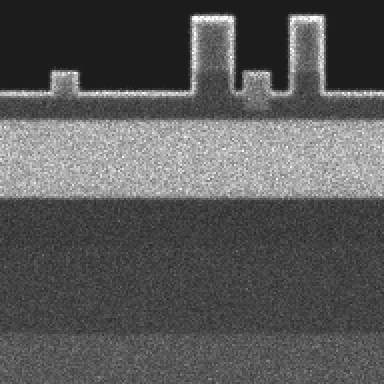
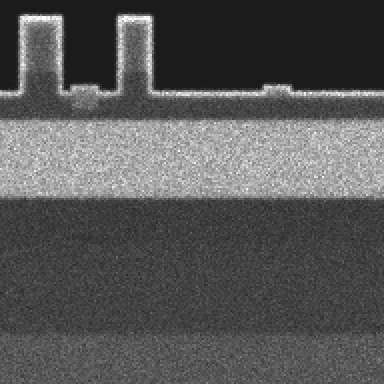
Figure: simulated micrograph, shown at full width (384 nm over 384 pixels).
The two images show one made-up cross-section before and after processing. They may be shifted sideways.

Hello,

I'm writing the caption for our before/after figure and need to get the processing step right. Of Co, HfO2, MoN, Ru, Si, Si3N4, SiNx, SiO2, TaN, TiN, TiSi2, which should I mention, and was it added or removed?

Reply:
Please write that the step removed Ru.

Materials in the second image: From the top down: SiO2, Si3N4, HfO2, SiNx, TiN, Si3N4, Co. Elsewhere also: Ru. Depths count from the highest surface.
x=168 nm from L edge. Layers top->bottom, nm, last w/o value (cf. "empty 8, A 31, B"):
empty 76, Si3N4 28, HfO2 78, SiNx 46, TiN 24, Si3N4 66, Co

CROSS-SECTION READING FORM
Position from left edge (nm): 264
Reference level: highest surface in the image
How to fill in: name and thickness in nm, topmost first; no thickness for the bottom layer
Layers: empty 70, Ru 12, Si3N4 22, HfO2 78, SiNx 46, TiN 24, Si3N4 66, Co